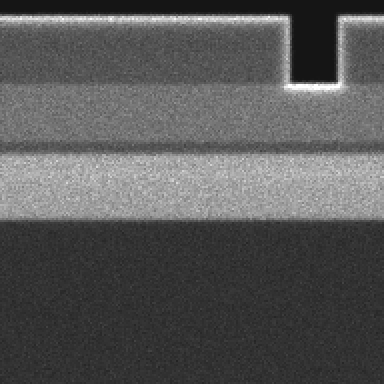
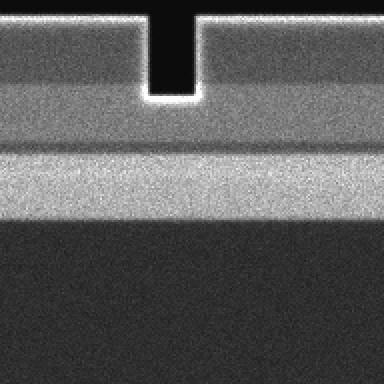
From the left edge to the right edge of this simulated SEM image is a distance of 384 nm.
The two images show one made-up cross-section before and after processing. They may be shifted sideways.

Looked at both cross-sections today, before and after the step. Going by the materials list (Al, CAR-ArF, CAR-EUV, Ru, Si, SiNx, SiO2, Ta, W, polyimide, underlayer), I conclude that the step removed SiO2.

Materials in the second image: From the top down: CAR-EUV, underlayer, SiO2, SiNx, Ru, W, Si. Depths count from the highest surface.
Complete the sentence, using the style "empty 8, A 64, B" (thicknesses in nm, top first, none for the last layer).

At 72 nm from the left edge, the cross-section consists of CAR-EUV 36, underlayer 32, SiO2 58, SiNx 12, Ru 16, W 50, Si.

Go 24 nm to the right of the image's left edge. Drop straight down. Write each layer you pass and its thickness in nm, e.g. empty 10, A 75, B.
CAR-EUV 36, underlayer 32, SiO2 58, SiNx 12, Ru 16, W 50, Si